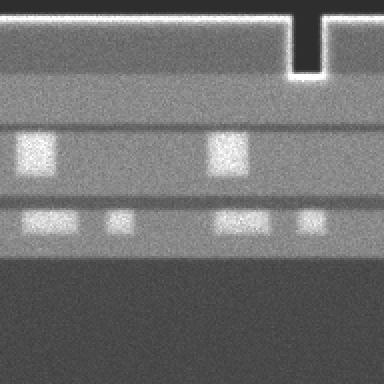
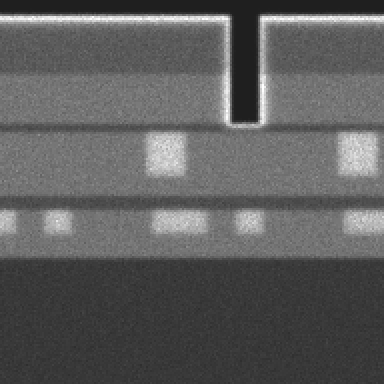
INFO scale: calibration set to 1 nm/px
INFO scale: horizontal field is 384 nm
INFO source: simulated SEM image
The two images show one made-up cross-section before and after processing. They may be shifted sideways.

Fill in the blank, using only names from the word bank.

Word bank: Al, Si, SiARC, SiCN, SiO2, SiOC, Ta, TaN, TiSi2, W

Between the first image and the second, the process removed SiO2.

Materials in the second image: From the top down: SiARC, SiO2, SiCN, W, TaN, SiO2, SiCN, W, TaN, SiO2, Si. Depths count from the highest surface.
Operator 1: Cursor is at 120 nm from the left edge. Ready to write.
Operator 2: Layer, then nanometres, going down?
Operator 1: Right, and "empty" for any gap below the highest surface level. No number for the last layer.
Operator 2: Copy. SiARC 58, SiO2 50, SiCN 8, SiO2 64, SiCN 14, SiO2 48, Si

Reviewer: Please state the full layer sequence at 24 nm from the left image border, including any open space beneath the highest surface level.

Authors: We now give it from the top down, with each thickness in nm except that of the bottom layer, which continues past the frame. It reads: SiARC 58, SiO2 50, SiCN 8, SiO2 64, SiCN 14, SiO2 48, Si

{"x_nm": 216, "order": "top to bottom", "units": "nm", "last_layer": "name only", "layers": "SiARC 58, SiO2 50, SiCN 8, SiO2 64, SiCN 14, SiO2 48, Si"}